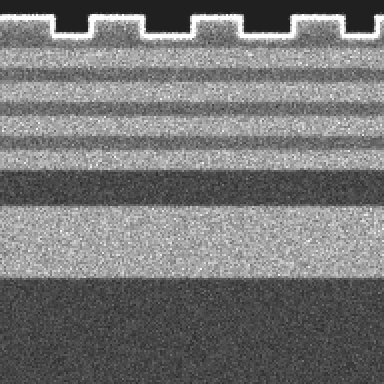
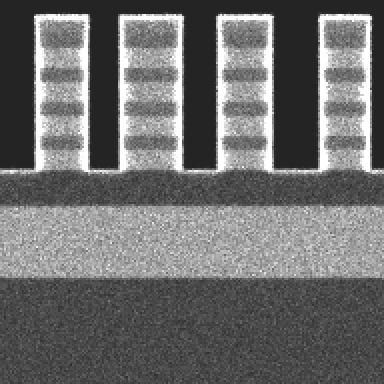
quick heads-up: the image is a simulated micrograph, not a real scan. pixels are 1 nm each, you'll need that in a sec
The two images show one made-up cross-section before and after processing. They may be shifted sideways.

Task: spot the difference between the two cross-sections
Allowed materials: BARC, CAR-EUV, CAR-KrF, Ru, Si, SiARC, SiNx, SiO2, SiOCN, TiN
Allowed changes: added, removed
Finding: removed SiO2 and SiOCN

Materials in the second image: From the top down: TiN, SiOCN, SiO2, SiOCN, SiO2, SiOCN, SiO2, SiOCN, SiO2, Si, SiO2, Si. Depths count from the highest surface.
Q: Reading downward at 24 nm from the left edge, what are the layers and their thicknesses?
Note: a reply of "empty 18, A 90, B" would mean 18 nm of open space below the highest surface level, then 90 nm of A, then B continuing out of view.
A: empty 154, Si 36, SiO2 72, Si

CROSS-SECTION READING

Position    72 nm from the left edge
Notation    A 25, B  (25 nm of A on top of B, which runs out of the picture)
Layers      TiN 18, SiOCN 14, SiO2 20, SiOCN 14, SiO2 20, SiOCN 14, SiO2 20, SiOCN 14, SiO2 20, Si 36, SiO2 72, Si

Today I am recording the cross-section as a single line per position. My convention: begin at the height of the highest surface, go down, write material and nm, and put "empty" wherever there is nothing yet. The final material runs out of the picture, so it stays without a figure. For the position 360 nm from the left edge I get TiN 18, SiOCN 14, SiO2 20, SiOCN 14, SiO2 20, SiOCN 14, SiO2 20, SiOCN 14, SiO2 20, Si 36, SiO2 72, Si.